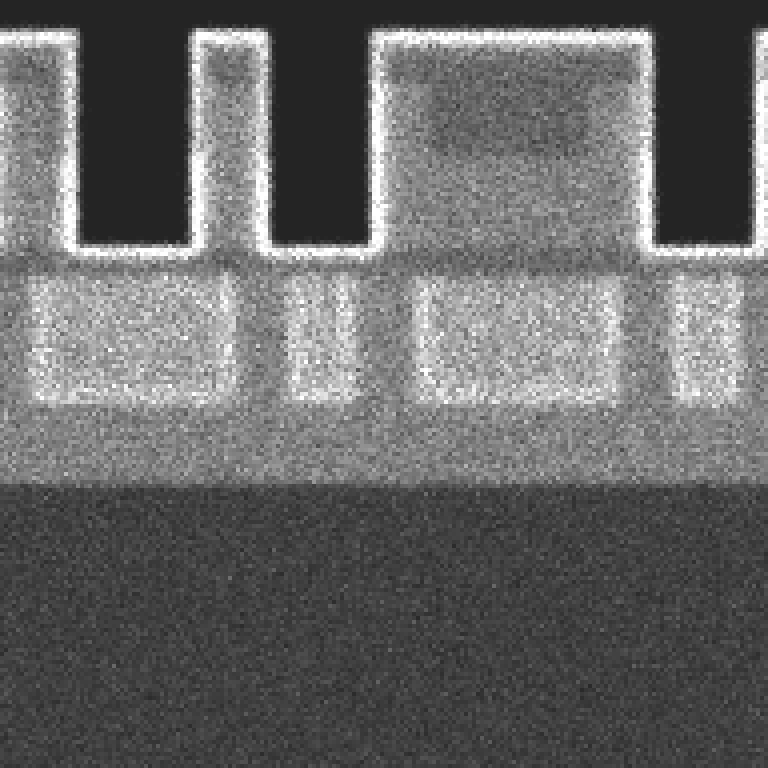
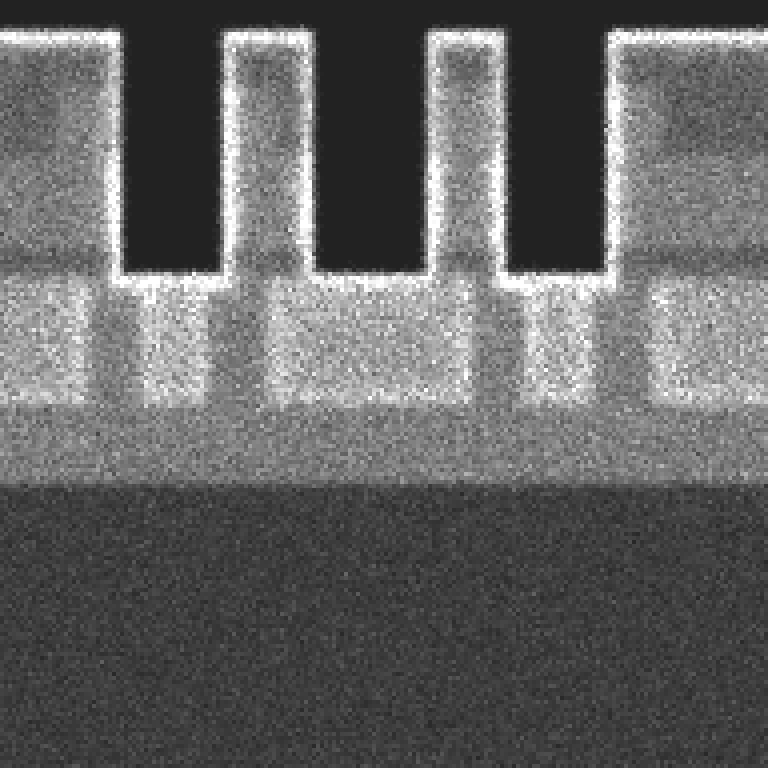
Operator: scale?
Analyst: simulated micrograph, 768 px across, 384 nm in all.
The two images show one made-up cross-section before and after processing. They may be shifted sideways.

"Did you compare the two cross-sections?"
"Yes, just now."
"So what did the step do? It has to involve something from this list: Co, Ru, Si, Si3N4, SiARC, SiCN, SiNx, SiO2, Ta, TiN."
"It removed Si3N4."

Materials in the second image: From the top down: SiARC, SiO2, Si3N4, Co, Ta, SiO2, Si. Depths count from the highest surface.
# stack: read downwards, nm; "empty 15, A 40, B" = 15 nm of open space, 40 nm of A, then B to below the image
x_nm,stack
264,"empty 122, Ta 64, SiO2 40, Si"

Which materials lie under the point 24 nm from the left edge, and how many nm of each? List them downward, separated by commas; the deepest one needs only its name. SiARC 62, SiO2 46, Si3N4 14, Co 56, Ta 8, SiO2 40, Si